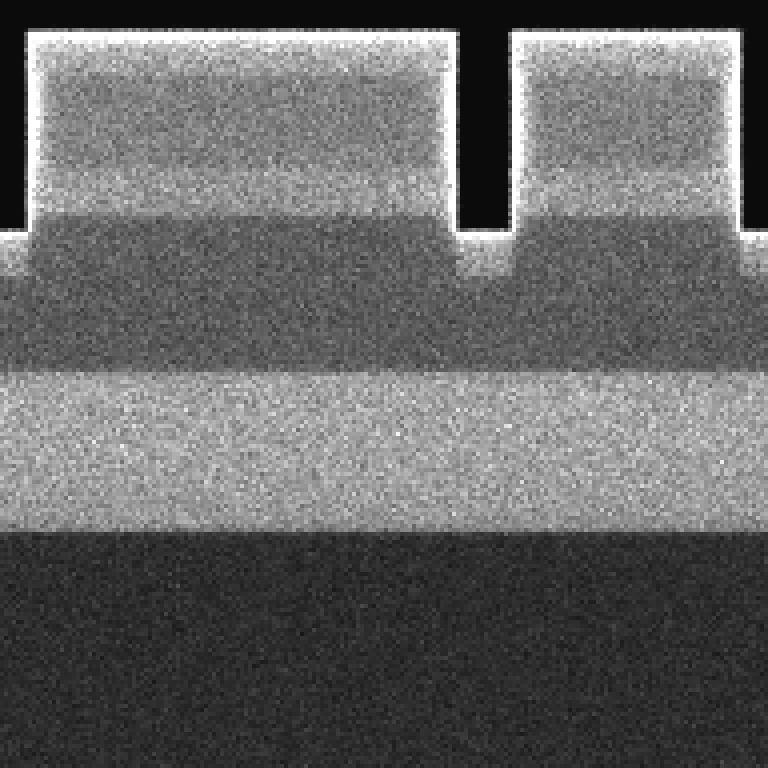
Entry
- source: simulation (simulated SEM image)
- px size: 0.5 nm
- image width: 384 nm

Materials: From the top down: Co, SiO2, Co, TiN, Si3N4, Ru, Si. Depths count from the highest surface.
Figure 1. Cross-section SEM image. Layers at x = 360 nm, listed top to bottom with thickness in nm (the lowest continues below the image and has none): Co 22, SiO2 46, Co 24, TiN 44, Si3N4 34, Ru 80, Si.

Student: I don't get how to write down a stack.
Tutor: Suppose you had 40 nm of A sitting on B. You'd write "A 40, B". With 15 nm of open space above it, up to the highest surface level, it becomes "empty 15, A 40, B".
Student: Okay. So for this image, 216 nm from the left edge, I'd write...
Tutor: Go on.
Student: Co 22, SiO2 46, Co 24, TiN 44, Si3N4 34, Ru 80, Si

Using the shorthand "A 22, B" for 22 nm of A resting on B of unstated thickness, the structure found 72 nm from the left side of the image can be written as Co 22, SiO2 46, Co 24, TiN 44, Si3N4 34, Ru 80, Si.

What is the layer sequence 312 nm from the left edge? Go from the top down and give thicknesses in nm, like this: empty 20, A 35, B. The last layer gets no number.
Co 22, SiO2 46, Co 24, TiN 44, Si3N4 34, Ru 80, Si